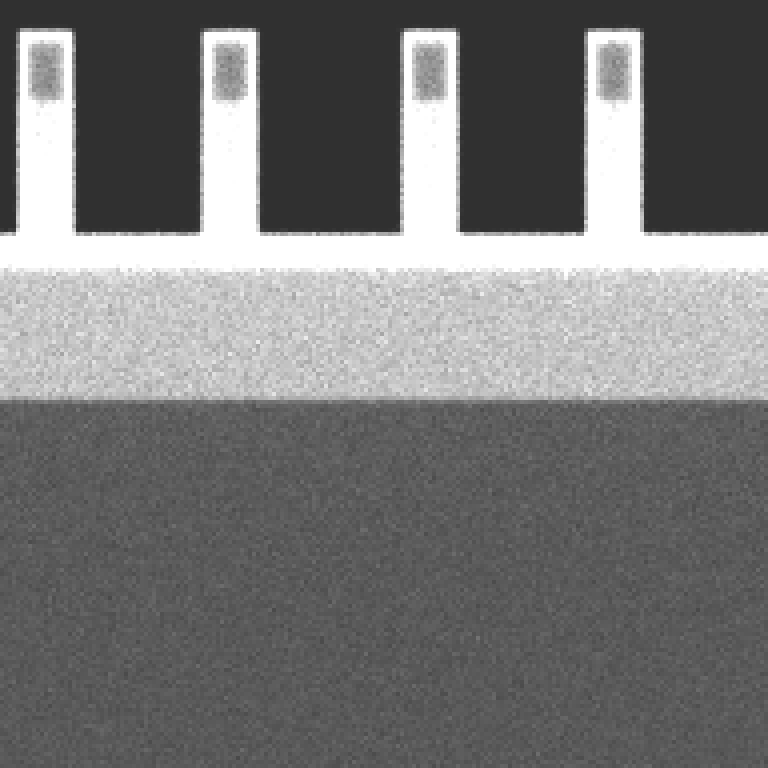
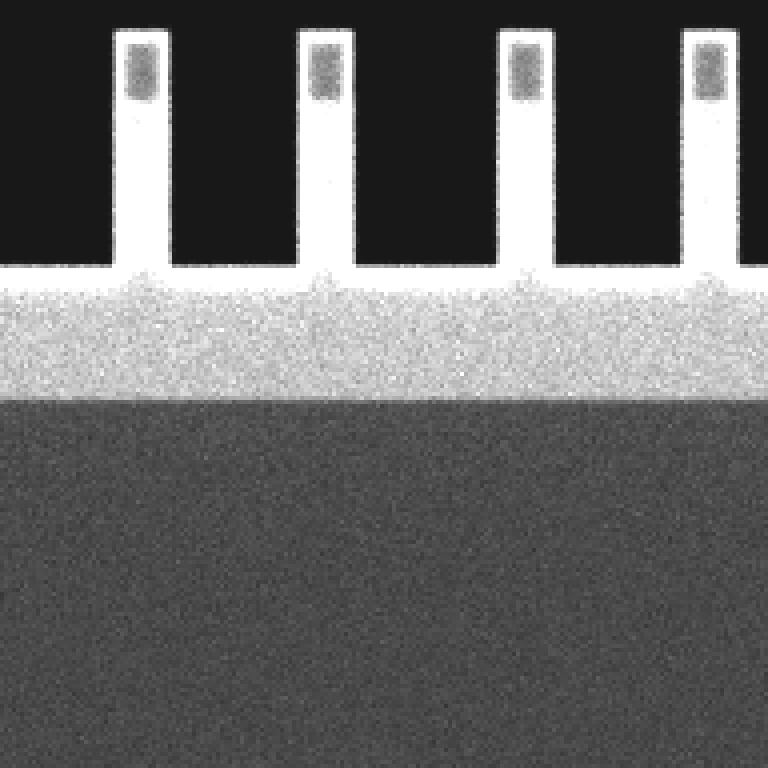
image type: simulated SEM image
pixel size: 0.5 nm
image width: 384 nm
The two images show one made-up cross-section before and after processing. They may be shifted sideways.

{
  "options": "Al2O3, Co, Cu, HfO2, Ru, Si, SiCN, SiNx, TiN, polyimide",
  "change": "removed",
  "material": "Ru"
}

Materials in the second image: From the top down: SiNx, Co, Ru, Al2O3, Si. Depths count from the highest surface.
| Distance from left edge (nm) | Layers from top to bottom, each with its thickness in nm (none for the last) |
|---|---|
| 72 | SiNx 34, Co 68, Ru 16, Al2O3 66, Si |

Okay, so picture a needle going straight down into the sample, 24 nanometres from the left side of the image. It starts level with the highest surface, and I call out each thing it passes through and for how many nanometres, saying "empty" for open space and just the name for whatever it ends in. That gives empty 118, Al2O3 66, Si